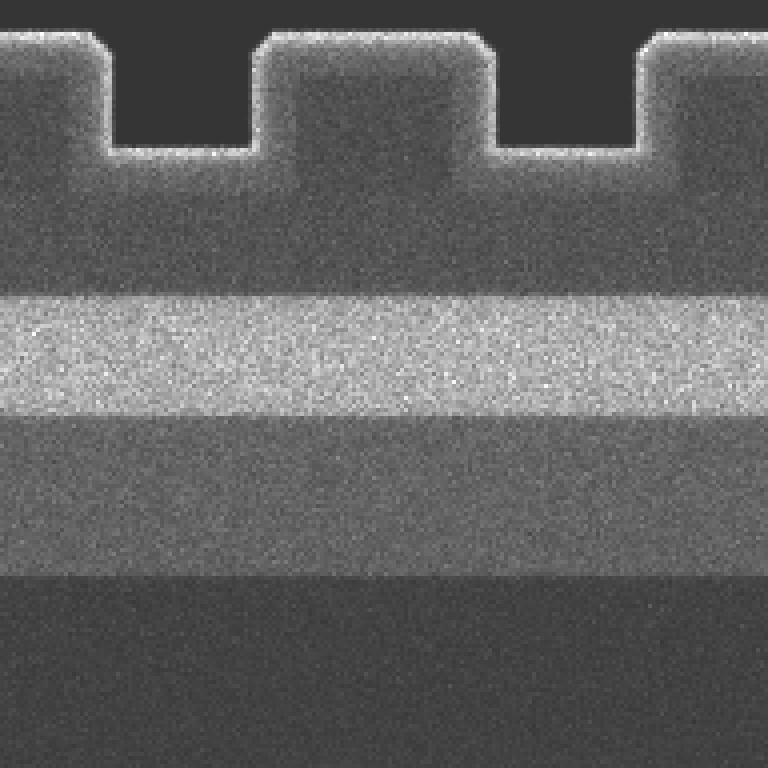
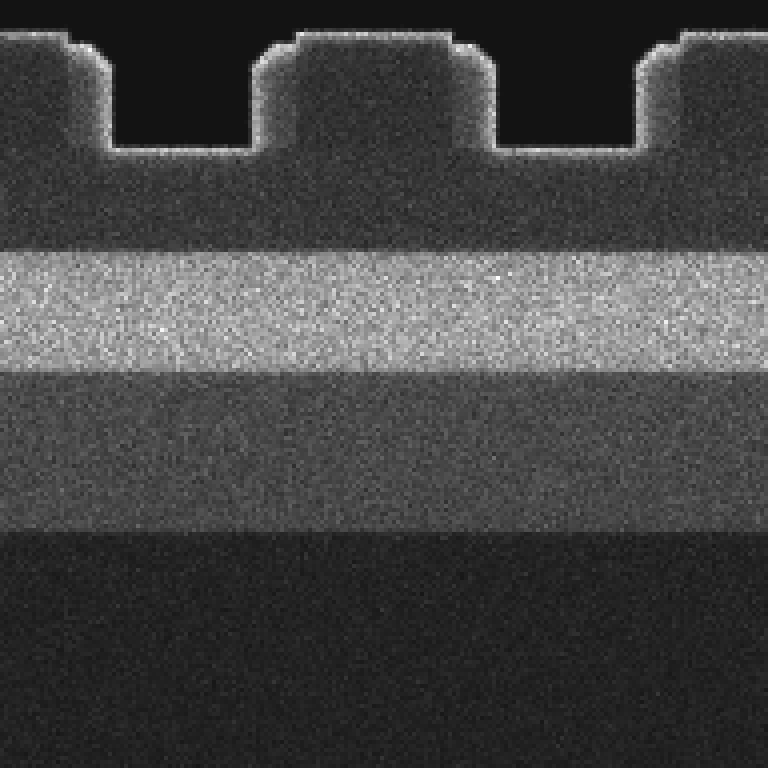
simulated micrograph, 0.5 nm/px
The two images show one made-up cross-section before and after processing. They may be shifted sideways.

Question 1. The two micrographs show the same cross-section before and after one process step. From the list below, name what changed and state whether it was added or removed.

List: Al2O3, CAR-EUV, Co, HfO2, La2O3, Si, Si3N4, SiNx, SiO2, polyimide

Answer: SiO2, removed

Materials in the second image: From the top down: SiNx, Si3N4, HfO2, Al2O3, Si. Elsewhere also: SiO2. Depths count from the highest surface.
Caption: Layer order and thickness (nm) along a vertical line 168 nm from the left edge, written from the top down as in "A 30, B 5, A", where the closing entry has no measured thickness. SiNx 58, Si3N4 52, HfO2 60, Al2O3 80, Si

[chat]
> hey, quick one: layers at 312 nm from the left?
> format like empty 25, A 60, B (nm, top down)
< empty 58, Si3N4 52, HfO2 60, Al2O3 80, Si